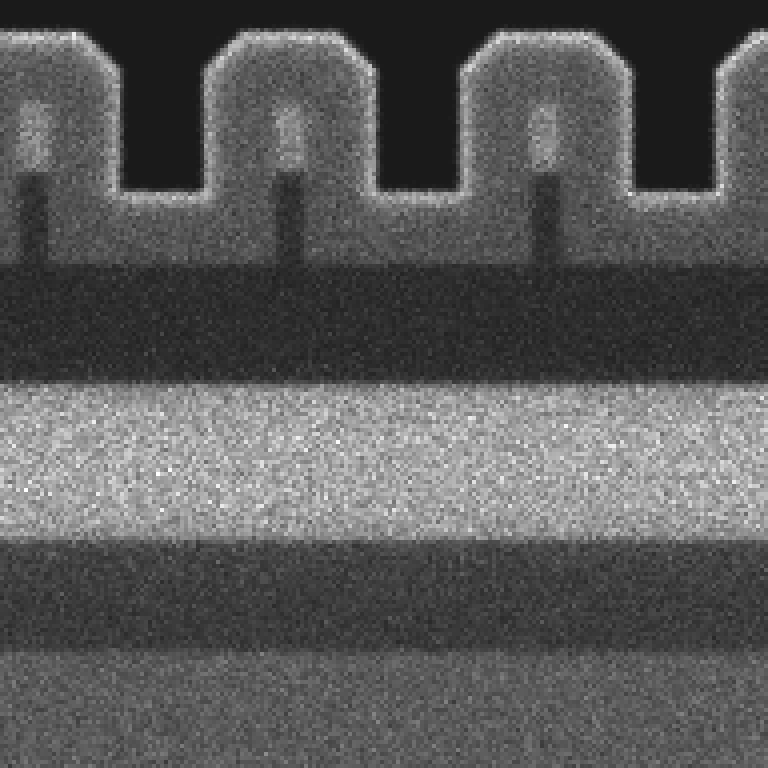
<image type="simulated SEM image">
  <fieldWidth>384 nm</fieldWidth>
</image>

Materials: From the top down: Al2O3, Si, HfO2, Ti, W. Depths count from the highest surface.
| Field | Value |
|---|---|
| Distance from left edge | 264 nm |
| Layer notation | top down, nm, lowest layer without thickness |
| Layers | Al2O3 116, Si 60, HfO2 78, Ti 56, W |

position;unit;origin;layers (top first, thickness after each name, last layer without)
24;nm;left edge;Al2O3 116, Si 60, HfO2 78, Ti 56, W